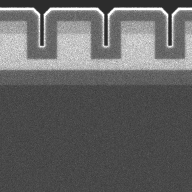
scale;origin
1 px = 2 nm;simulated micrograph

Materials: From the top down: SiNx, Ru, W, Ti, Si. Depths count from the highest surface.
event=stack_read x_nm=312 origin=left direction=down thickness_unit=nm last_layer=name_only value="SiNx 102, W 22, Ti 30, Si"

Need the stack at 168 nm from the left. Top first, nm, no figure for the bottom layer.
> SiNx 26, Ru 26, W 72, Ti 30, Si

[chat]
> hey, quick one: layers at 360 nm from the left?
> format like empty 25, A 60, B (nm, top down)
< SiNx 102, W 22, Ti 30, Si